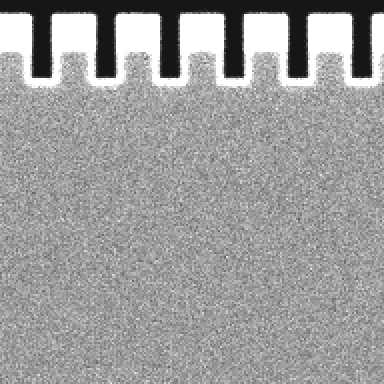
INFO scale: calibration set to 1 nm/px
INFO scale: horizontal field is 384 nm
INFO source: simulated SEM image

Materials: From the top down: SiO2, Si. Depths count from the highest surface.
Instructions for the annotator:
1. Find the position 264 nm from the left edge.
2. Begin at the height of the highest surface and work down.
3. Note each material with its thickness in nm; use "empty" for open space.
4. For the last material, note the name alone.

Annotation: SiO2 34, Si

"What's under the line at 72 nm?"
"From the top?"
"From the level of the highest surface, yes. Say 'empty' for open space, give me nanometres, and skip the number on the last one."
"SiO2 34, Si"